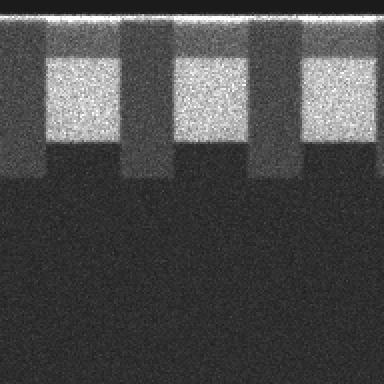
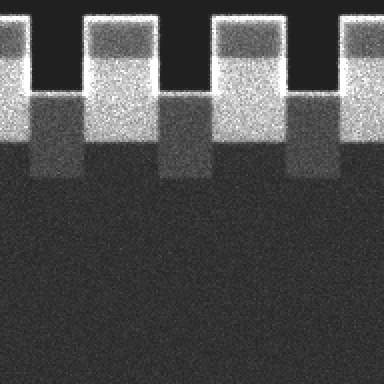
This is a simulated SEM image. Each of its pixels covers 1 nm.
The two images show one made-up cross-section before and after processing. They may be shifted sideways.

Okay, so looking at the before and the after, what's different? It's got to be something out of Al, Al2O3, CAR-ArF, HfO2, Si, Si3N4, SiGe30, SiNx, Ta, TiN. Si3N4, removed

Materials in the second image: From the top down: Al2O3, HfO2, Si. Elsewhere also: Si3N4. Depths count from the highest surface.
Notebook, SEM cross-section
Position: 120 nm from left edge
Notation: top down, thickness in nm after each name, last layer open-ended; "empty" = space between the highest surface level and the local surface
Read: Al2O3 42, HfO2 84, Si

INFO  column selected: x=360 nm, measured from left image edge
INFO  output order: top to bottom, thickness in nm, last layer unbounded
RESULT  Al2O3 42, HfO2 84, Si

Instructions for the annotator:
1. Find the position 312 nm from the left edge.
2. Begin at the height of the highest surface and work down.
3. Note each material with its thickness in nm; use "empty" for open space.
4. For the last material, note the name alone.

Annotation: empty 76, Si3N4 86, Si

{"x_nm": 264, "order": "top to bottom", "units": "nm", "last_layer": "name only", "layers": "Al2O3 42, HfO2 84, Si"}